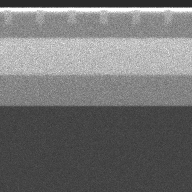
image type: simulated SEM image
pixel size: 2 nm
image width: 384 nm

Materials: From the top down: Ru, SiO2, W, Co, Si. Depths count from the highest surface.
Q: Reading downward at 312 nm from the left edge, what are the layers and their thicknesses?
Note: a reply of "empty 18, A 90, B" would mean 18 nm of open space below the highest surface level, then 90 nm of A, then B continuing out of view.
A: SiO2 60, W 74, Co 62, Si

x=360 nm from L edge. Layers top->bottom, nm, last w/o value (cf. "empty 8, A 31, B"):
SiO2 60, W 74, Co 62, Si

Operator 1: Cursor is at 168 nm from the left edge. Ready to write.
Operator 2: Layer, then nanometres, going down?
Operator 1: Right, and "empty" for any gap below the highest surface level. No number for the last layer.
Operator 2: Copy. SiO2 60, W 74, Co 62, Si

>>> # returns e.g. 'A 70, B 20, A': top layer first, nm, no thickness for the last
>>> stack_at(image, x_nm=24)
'SiO2 60, W 74, Co 62, Si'